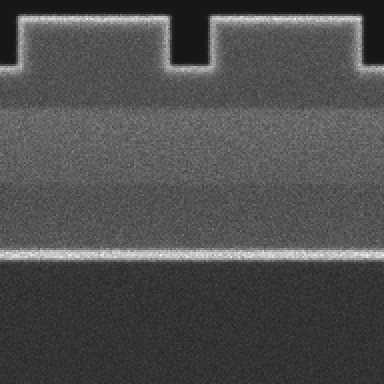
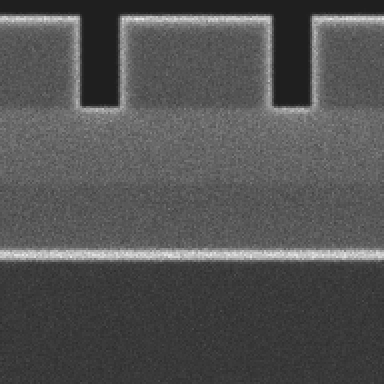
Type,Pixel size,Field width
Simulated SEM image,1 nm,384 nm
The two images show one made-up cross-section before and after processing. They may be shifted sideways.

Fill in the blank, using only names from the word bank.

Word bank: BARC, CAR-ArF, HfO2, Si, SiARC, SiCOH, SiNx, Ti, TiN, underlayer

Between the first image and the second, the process removed underlayer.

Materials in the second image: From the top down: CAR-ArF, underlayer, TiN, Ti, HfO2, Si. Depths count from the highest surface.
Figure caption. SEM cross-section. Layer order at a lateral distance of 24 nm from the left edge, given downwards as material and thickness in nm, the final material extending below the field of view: CAR-ArF 50, underlayer 42, TiN 76, Ti 66, HfO2 10, Si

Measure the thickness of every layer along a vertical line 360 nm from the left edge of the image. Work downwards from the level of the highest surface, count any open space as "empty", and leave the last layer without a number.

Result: CAR-ArF 50, underlayer 42, TiN 76, Ti 66, HfO2 10, Si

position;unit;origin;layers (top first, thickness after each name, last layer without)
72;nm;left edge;CAR-ArF 50, underlayer 42, TiN 76, Ti 66, HfO2 10, Si